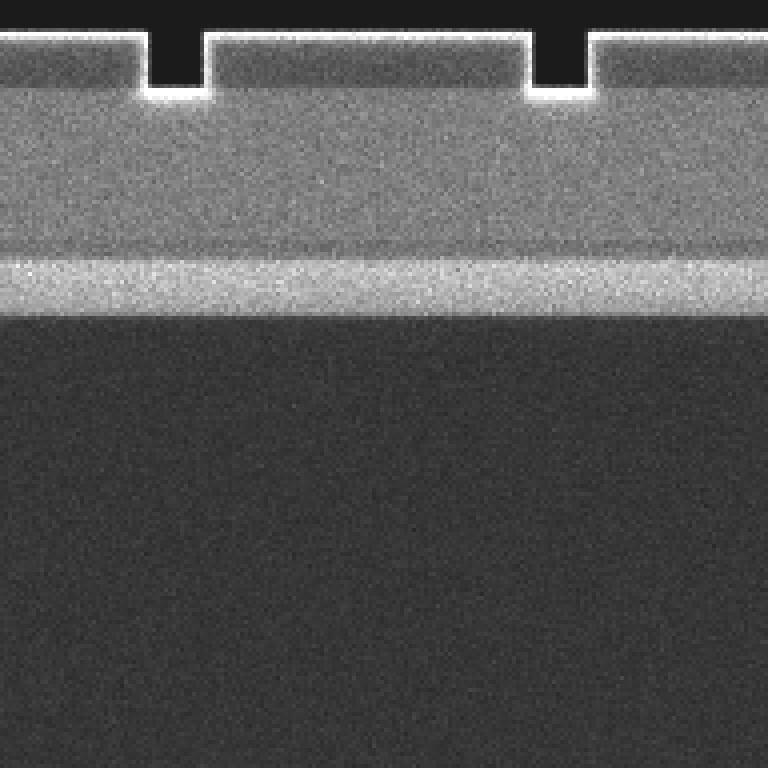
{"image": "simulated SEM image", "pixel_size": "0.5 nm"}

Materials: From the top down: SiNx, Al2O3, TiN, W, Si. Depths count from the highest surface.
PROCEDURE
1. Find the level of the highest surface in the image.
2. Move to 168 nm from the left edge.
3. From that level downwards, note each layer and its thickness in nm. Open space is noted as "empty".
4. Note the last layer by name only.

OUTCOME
SiNx 28, Al2O3 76, TiN 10, W 28, Si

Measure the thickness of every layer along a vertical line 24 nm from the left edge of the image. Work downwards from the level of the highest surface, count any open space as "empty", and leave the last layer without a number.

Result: SiNx 28, Al2O3 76, TiN 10, W 28, Si